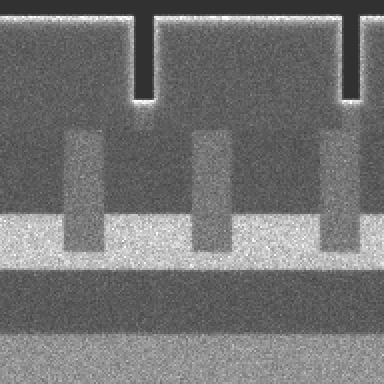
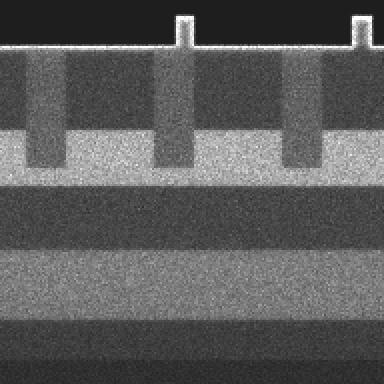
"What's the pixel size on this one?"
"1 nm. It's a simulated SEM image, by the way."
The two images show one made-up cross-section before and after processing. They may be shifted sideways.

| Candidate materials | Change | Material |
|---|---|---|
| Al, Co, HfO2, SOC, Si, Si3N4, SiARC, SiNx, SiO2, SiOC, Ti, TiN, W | removed | SOC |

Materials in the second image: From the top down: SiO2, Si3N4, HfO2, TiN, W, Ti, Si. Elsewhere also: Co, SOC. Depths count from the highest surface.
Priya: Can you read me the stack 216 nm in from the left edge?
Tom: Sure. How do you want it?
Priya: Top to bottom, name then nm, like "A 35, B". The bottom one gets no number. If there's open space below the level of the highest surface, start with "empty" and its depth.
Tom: empty 30, Si3N4 84, HfO2 56, TiN 64, W 70, Ti 40, Si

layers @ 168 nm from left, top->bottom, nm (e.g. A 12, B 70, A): empty 30, Co 122, HfO2 18, TiN 64, W 70, Ti 40, Si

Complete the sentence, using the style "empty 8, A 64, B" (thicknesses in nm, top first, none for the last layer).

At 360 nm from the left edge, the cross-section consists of SiO2 30, Si3N4 84, HfO2 56, TiN 64, W 70, Ti 40, Si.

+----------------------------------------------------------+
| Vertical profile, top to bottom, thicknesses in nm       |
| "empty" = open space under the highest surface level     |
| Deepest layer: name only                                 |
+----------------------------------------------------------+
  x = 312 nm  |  empty 30, Co 122, HfO2 18, TiN 64, W 70, Ti 40, Si